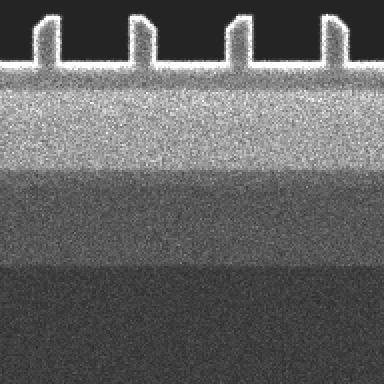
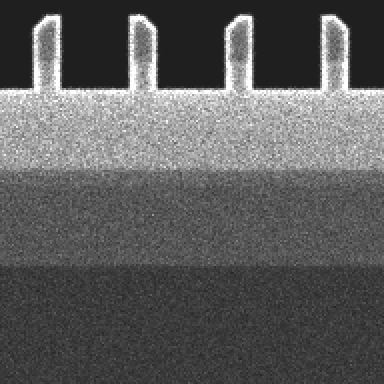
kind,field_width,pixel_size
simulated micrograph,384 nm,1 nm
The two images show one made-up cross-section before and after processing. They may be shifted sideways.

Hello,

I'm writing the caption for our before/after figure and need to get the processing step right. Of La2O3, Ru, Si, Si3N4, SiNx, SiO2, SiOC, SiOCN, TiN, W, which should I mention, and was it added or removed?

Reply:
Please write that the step removed SiO2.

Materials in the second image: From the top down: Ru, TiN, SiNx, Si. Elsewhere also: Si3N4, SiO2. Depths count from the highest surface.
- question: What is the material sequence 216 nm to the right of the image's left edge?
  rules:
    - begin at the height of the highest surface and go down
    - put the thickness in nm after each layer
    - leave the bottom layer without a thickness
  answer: empty 74, Ru 80, TiN 16, SiNx 80, Si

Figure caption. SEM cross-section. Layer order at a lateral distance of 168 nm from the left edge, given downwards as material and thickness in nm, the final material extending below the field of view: empty 74, Ru 80, TiN 16, SiNx 80, Si